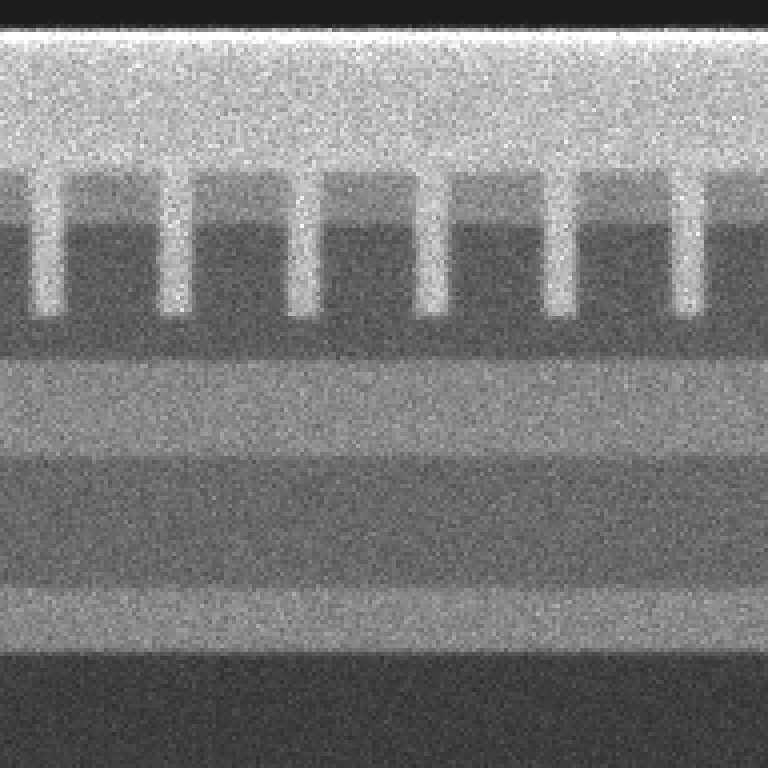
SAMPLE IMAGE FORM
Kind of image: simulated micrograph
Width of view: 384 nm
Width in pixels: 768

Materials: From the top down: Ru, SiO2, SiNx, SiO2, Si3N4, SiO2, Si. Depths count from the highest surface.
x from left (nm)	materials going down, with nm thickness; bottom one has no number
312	Ru 70, SiO2 26, SiNx 68, SiO2 48, Si3N4 66, SiO2 32, Si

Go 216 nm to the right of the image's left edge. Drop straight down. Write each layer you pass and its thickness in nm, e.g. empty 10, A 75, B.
Ru 142, SiNx 22, SiO2 48, Si3N4 66, SiO2 32, Si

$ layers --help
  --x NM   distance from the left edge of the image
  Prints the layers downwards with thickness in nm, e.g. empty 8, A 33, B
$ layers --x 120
Ru 70, SiO2 26, SiNx 68, SiO2 48, Si3N4 66, SiO2 32, Si